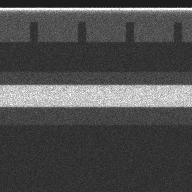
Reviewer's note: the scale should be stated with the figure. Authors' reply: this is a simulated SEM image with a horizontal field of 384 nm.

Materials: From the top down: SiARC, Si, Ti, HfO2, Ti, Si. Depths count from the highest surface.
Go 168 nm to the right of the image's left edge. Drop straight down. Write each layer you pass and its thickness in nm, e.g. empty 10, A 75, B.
SiARC 28, Si 100, Ti 26, HfO2 44, Ti 36, Si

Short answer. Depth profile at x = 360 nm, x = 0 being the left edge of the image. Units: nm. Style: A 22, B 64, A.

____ SiARC 28, Si 100, Ti 26, HfO2 44, Ti 36, Si